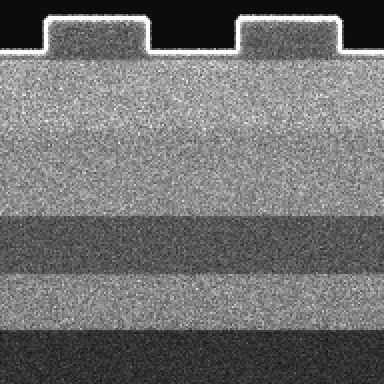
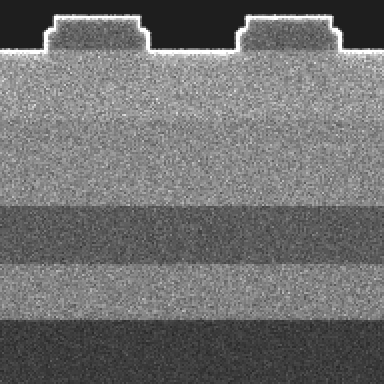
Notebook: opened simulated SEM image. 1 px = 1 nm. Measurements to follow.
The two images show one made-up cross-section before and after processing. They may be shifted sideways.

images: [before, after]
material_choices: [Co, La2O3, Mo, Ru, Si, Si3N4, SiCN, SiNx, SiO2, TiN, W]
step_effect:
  removed: Si3N4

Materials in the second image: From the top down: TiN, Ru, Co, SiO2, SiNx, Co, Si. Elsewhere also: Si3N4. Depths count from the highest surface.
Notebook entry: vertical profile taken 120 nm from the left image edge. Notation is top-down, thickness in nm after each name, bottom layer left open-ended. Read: TiN 34, Ru 70, Co 24, SiO2 62, SiNx 58, Co 56, Si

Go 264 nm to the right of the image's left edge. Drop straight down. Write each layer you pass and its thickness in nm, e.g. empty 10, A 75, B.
TiN 34, Ru 70, Co 24, SiO2 62, SiNx 58, Co 56, Si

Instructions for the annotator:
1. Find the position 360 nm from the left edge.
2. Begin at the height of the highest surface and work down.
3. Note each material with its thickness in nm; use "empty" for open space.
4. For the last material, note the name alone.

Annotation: empty 34, Ru 70, Co 24, SiO2 62, SiNx 58, Co 56, Si